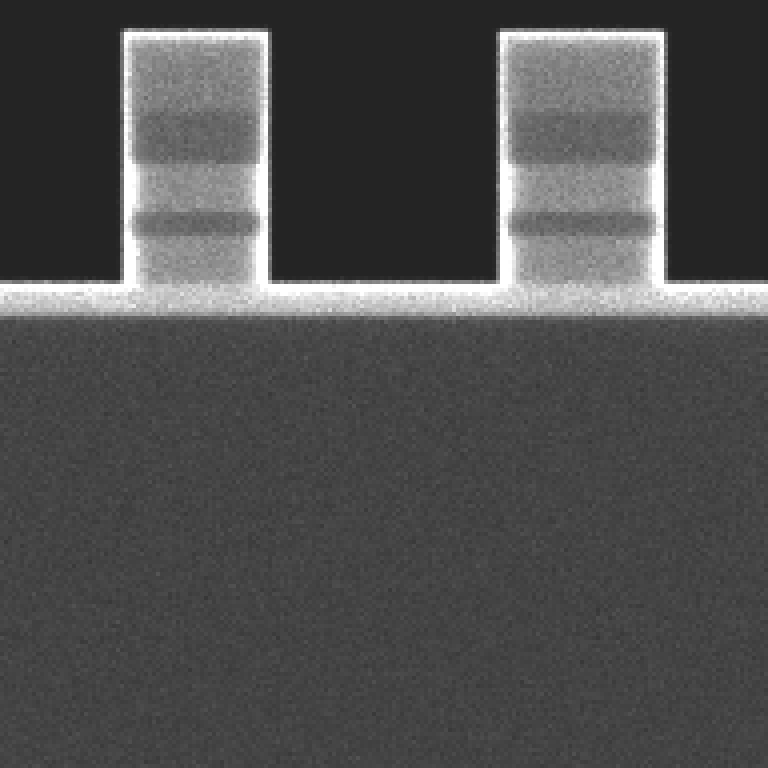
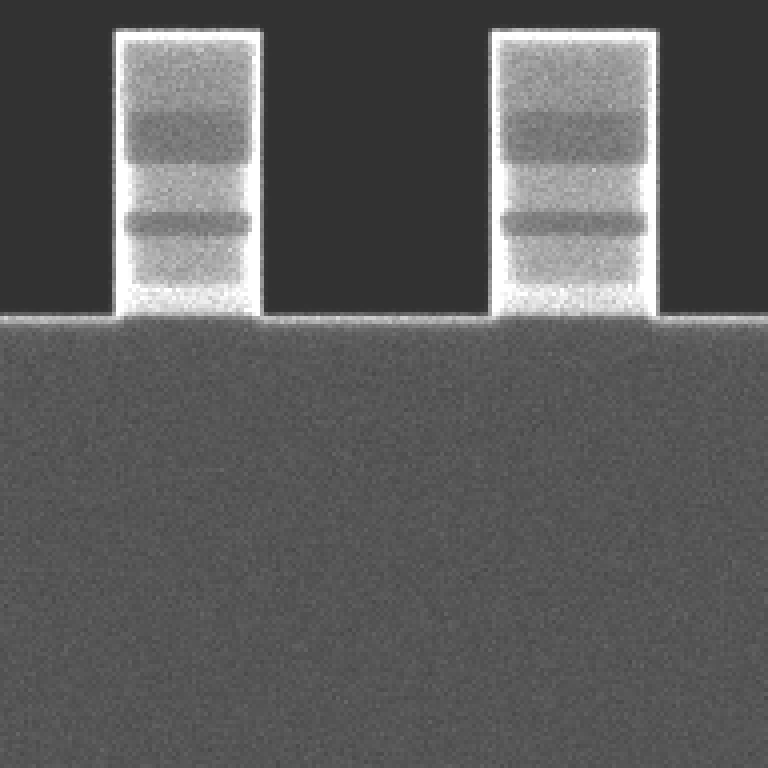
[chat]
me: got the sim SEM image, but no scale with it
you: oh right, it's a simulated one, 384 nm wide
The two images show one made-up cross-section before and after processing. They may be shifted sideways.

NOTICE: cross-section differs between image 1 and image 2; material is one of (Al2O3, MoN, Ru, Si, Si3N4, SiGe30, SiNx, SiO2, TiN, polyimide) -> removed: Ru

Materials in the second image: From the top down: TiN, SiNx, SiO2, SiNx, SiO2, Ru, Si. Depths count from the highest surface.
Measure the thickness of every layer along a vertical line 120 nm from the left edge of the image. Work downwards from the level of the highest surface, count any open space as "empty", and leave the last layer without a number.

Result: TiN 40, SiNx 26, SiO2 24, SiNx 12, SiO2 24, Ru 16, Si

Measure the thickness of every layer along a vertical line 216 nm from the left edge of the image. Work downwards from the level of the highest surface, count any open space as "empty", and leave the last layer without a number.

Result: empty 142, Si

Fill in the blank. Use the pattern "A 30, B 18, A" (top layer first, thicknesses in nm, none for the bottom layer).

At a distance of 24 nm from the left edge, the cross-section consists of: empty 142, Si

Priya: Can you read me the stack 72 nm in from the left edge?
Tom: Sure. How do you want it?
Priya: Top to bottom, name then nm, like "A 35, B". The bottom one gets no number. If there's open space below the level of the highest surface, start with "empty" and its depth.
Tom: TiN 40, SiNx 26, SiO2 24, SiNx 12, SiO2 24, Ru 16, Si